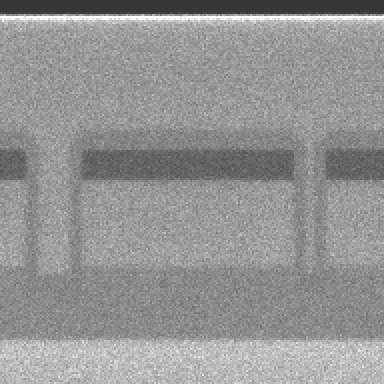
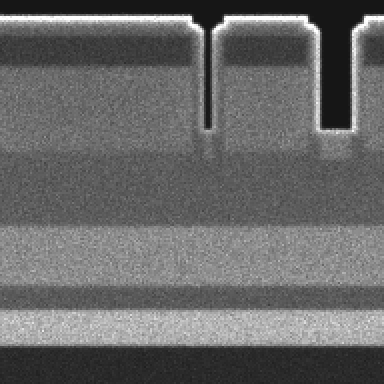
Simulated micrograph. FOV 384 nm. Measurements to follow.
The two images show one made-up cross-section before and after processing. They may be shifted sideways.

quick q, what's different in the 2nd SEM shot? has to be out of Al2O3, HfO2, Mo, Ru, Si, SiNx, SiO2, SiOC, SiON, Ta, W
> Ru removed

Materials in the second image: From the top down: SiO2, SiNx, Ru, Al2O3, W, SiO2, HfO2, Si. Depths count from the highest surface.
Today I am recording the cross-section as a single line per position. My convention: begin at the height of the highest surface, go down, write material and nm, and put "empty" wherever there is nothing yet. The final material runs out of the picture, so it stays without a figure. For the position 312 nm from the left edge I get empty 8, SiO2 156, Al2O3 46, W 60, SiO2 24, HfO2 36, Si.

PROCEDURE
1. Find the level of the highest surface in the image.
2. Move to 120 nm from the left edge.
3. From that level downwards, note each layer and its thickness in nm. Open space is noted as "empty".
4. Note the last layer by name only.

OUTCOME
SiO2 20, SiNx 30, Ru 86, Al2O3 74, W 60, SiO2 24, HfO2 36, Si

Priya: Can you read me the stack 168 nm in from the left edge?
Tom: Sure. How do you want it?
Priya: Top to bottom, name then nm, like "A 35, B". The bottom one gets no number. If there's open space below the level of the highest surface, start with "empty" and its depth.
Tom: SiO2 20, SiNx 30, Ru 86, Al2O3 74, W 60, SiO2 24, HfO2 36, Si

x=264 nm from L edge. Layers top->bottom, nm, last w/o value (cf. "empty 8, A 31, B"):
SiO2 20, SiNx 30, Ru 86, Al2O3 74, W 60, SiO2 24, HfO2 36, Si